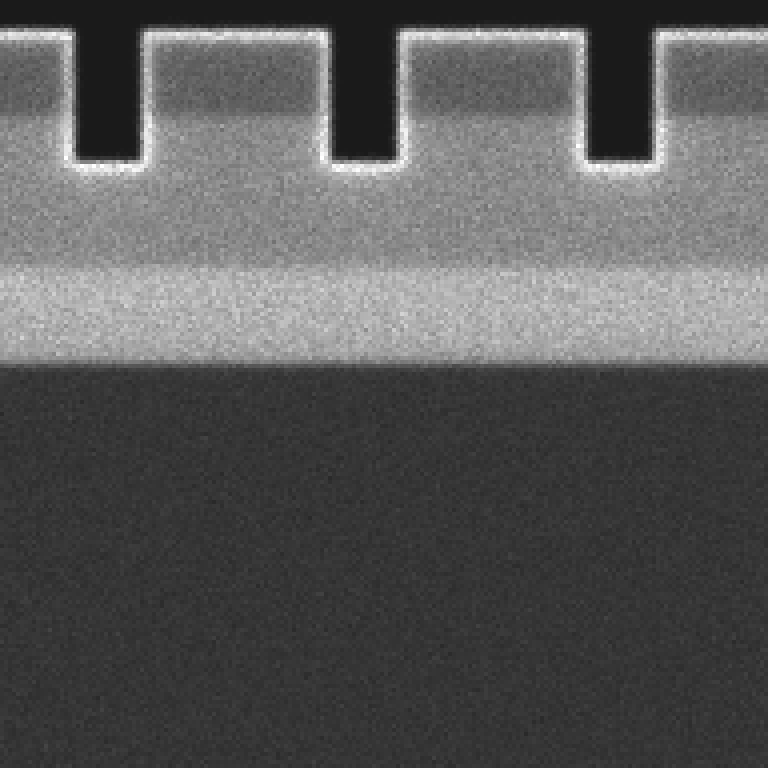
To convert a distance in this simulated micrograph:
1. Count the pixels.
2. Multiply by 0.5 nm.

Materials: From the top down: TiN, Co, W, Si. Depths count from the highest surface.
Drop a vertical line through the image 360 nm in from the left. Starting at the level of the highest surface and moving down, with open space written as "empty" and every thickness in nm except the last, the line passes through TiN 42, Co 76, W 48, Si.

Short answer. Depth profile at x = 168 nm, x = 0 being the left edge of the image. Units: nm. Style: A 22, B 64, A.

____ empty 66, Co 52, W 48, Si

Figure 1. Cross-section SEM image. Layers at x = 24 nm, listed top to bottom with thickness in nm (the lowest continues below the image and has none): TiN 42, Co 76, W 48, Si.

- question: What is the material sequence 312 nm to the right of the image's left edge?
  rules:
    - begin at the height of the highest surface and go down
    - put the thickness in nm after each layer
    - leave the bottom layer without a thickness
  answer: empty 66, Co 52, W 48, Si